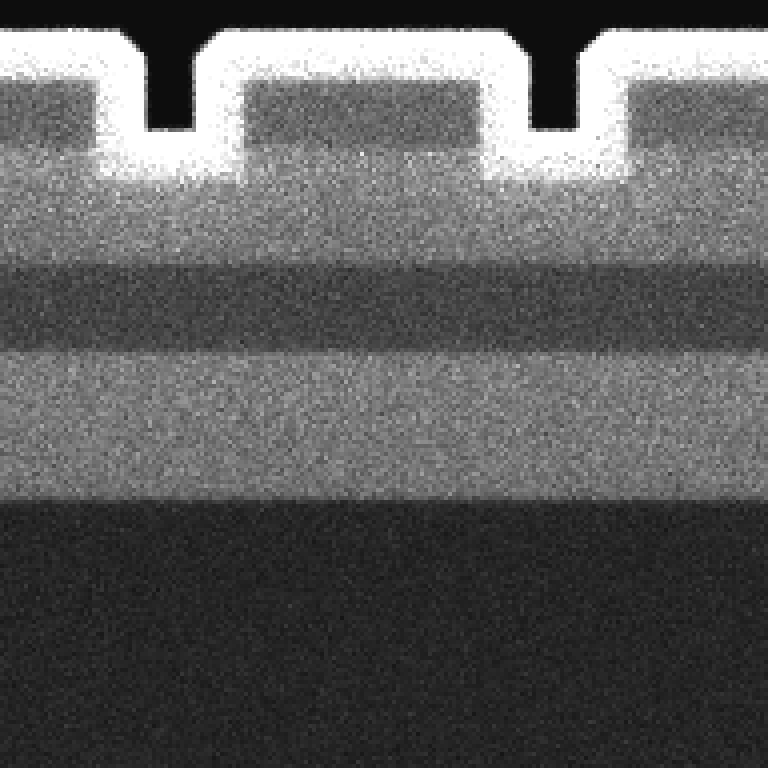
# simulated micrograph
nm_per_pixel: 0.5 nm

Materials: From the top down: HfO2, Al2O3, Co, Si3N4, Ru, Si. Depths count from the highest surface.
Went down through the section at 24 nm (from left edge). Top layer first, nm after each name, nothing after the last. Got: HfO2 24, Al2O3 34, Co 58, Si3N4 44, Ru 74, Si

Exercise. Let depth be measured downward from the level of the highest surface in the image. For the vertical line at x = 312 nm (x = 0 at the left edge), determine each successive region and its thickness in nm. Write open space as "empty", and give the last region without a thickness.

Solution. HfO2 74, Co 42, Si3N4 44, Ru 74, Si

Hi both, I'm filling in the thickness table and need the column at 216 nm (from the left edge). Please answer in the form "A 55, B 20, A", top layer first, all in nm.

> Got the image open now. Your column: HfO2 24, Al2O3 34, Co 58, Si3N4 44, Ru 74, Si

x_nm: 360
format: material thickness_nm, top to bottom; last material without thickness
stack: HfO2 24, Al2O3 34, Co 58, Si3N4 44, Ru 74, Si